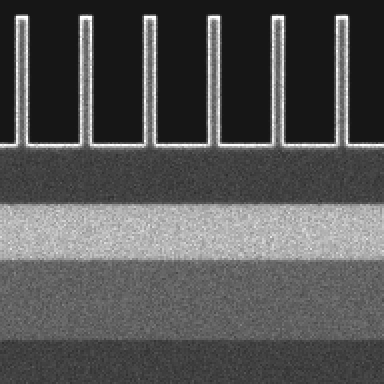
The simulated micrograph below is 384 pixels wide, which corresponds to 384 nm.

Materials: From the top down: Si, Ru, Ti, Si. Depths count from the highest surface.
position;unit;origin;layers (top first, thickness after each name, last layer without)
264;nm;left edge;empty 128, Si 60, Ru 56, Ti 80, Si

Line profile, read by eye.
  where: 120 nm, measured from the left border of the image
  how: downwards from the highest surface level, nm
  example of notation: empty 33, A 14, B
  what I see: empty 128, Si 60, Ru 56, Ti 80, Si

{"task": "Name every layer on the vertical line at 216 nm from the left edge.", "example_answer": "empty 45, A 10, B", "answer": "Si 188, Ru 56, Ti 80, Si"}